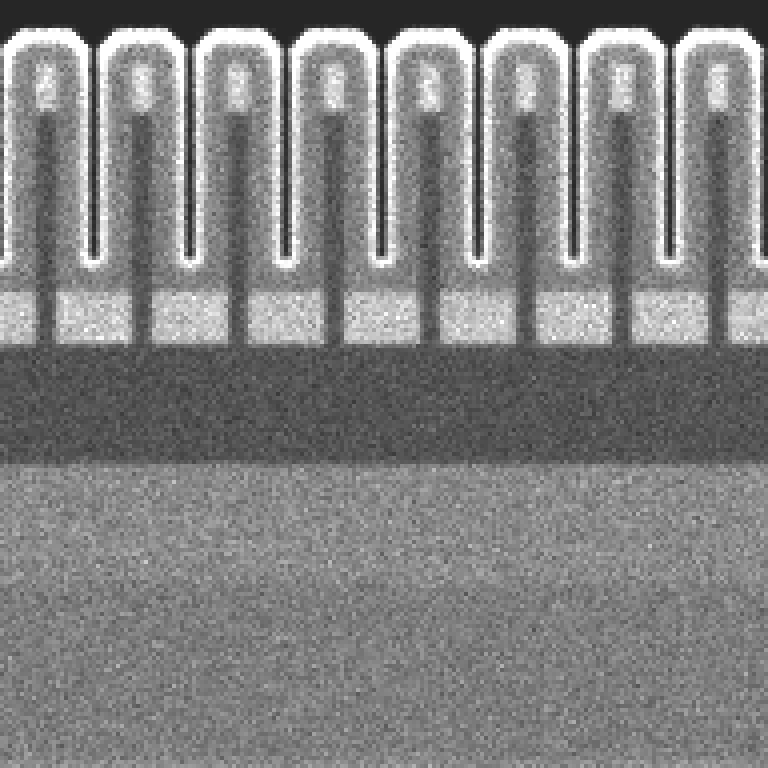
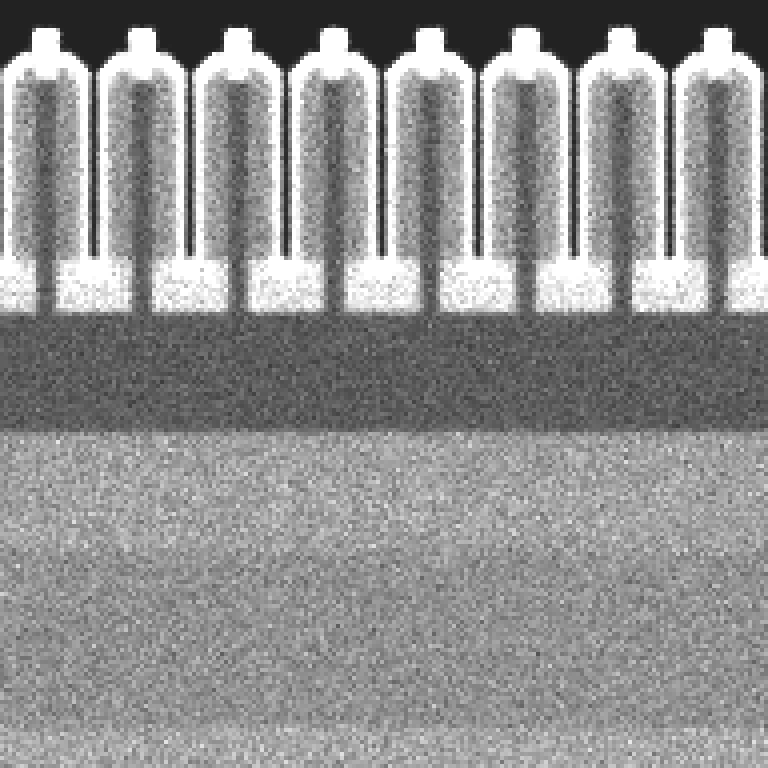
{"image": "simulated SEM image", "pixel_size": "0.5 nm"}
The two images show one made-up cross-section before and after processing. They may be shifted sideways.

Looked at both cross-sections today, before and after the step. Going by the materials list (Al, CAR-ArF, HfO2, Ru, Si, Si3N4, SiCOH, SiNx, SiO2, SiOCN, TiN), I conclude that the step removed SiNx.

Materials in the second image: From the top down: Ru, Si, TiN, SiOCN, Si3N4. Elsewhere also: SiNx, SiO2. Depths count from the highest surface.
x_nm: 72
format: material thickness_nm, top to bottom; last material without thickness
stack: Ru 24, Si 176, TiN 60, SiOCN 88, Si3N4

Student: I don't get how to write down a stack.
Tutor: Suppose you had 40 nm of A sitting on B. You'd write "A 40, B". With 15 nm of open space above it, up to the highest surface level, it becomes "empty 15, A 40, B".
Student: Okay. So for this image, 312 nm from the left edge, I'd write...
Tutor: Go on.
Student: Ru 24, Si 176, TiN 60, SiOCN 88, Si3N4